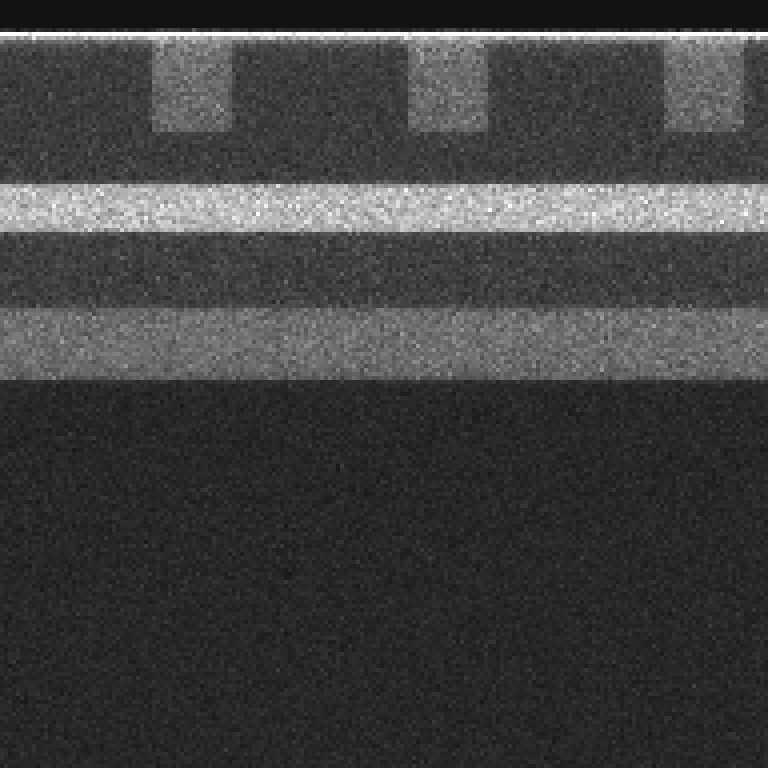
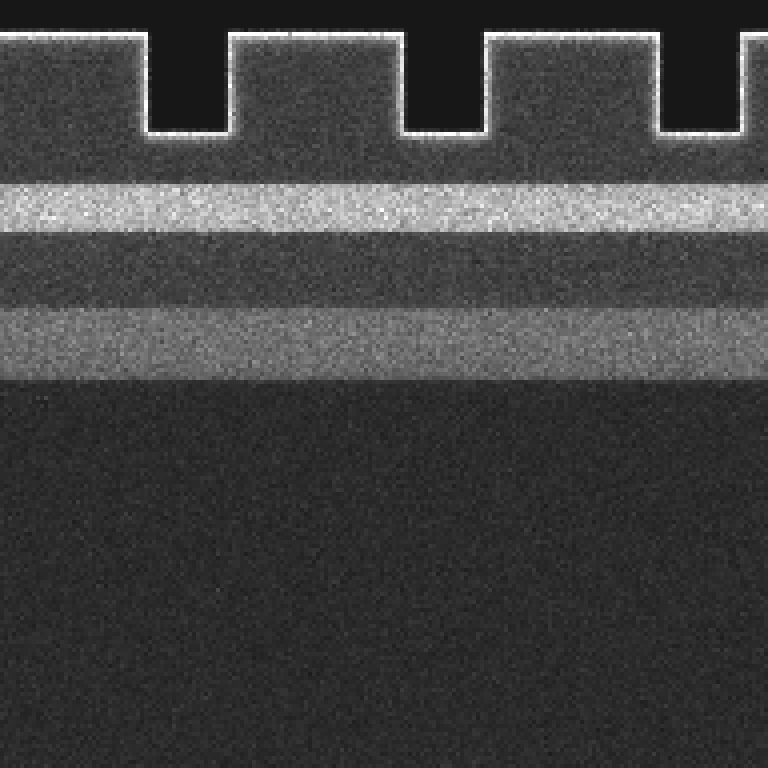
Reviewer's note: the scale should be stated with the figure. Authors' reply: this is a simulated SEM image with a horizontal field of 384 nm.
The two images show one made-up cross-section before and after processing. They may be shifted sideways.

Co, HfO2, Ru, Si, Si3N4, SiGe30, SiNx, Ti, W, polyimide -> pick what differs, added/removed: Co removed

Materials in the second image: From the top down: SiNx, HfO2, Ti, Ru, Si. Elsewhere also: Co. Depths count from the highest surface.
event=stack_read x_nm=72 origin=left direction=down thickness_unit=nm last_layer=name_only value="SiNx 76, HfO2 24, Ti 38, Ru 36, Si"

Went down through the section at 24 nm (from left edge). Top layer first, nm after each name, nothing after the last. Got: SiNx 76, HfO2 24, Ti 38, Ru 36, Si